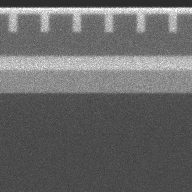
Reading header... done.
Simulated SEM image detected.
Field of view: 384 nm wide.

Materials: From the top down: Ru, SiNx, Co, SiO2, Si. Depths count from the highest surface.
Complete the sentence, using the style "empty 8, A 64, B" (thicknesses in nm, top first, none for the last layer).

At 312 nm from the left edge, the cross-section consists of Ru 12, SiNx 84, Co 28, SiO2 46, Si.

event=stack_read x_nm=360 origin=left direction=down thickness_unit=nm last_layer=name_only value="Ru 12, SiNx 84, Co 28, SiO2 46, Si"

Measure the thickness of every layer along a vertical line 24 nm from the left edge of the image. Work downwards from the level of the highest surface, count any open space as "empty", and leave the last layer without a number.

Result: Ru 48, SiNx 48, Co 28, SiO2 46, Si